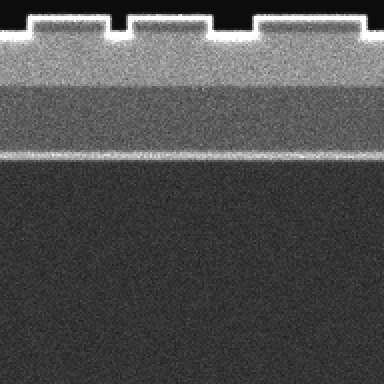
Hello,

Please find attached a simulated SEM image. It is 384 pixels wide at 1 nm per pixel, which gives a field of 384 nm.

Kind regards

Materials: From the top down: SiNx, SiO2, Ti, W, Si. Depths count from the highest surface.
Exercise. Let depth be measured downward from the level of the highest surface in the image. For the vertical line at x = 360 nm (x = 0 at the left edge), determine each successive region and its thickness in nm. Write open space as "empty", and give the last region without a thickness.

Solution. SiNx 16, SiO2 54, Ti 66, W 8, Si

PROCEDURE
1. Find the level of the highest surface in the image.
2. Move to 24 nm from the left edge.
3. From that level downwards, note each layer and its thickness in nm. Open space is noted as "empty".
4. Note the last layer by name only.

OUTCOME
empty 16, SiO2 54, Ti 66, W 8, Si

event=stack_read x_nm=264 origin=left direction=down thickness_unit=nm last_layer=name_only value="SiNx 16, SiO2 54, Ti 66, W 8, Si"